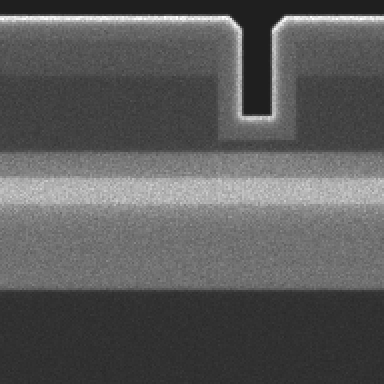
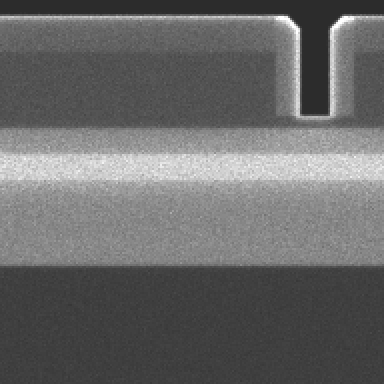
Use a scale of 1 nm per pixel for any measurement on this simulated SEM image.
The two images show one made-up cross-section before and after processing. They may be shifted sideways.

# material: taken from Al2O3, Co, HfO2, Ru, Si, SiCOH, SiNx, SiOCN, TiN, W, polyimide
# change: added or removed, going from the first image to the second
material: Al2O3
change: removed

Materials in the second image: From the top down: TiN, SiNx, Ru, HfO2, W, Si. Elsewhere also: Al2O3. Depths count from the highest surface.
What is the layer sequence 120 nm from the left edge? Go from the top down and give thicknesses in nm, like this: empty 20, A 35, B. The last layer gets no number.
TiN 36, SiNx 76, Ru 26, HfO2 26, W 86, Si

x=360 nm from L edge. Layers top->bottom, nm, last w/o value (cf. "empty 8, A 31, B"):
TiN 36, SiNx 76, Ru 26, HfO2 26, W 86, Si